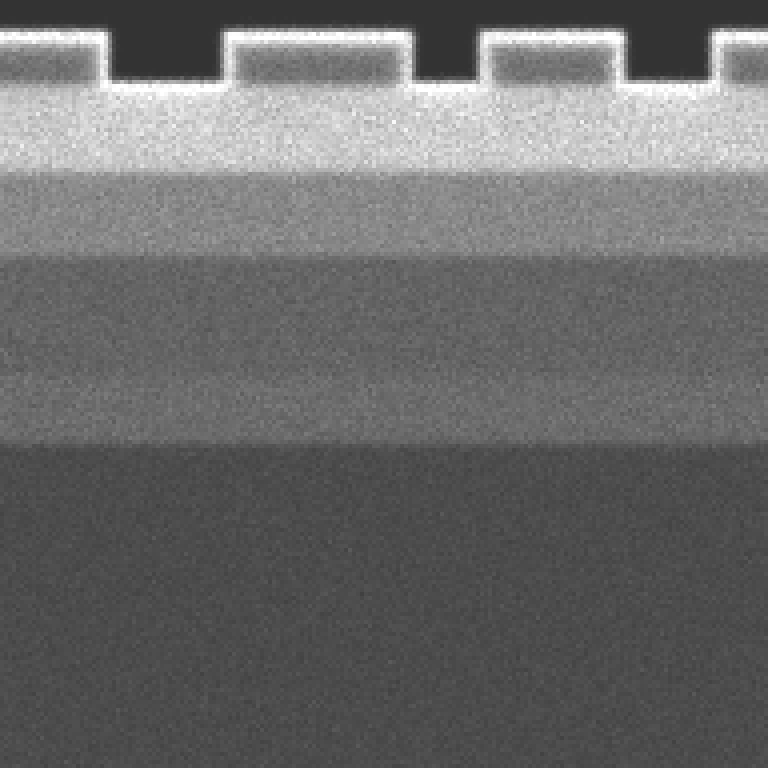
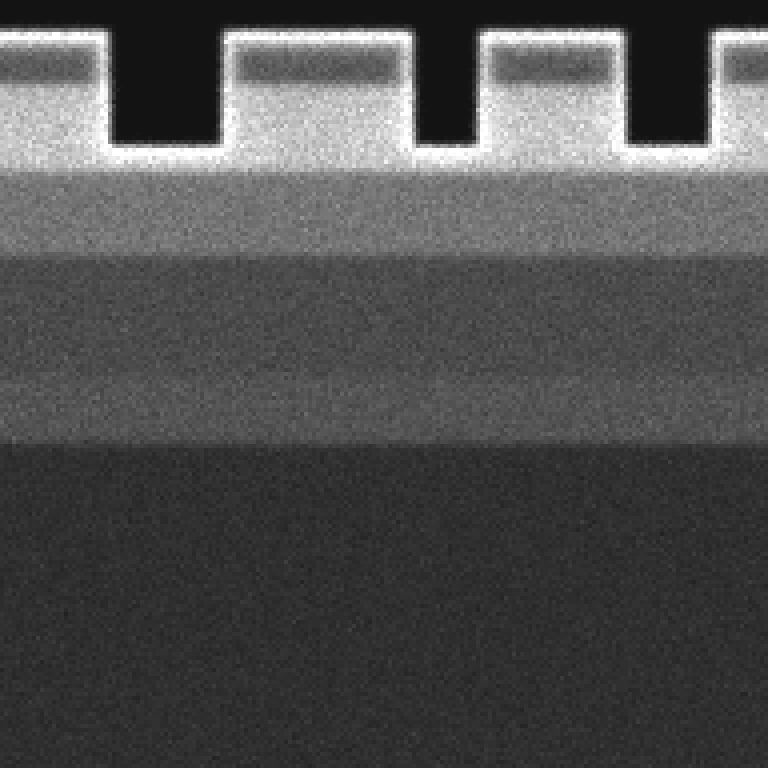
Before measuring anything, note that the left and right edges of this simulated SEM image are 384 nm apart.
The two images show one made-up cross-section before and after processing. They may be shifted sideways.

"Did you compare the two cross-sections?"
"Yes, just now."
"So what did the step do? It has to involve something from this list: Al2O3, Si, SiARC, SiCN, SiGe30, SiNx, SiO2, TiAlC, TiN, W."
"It removed W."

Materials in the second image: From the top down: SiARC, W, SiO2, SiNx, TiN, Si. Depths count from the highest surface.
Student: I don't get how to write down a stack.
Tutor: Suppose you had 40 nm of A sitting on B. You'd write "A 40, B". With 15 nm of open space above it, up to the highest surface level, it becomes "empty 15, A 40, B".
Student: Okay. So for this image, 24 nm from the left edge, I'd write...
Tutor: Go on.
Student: SiARC 26, W 44, SiO2 42, SiNx 60, TiN 34, Si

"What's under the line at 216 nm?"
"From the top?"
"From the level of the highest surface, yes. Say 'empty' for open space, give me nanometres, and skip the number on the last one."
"empty 58, W 12, SiO2 42, SiNx 60, TiN 34, Si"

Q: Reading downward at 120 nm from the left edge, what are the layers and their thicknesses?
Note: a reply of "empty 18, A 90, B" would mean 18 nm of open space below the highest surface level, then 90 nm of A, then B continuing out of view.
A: SiARC 26, W 44, SiO2 42, SiNx 60, TiN 34, Si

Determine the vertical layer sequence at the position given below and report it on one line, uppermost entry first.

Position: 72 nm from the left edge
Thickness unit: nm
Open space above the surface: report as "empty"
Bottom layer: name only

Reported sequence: empty 58, W 12, SiO2 42, SiNx 60, TiN 34, Si